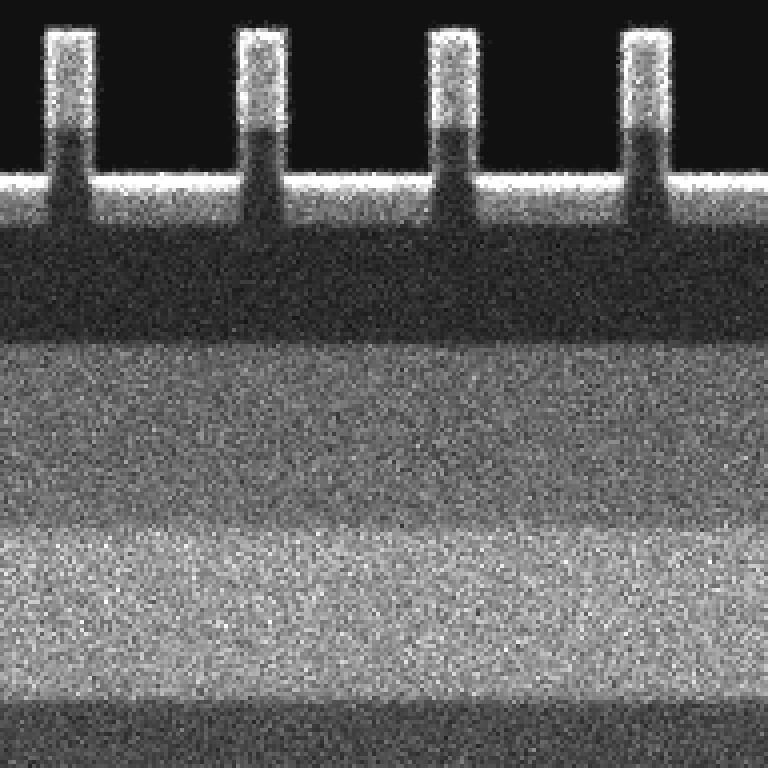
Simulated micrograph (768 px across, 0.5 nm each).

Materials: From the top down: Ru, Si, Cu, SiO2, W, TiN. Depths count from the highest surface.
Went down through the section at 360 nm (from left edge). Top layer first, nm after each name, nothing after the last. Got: empty 72, SiO2 24, Si 60, Cu 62, SiO2 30, W 86, TiN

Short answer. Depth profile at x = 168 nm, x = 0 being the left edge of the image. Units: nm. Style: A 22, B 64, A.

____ empty 72, SiO2 24, Si 60, Cu 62, SiO2 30, W 86, TiN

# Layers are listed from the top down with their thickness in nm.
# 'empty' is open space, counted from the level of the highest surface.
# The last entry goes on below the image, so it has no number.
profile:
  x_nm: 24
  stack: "Ru 48, Si 108, Cu 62, SiO2 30, W 86, TiN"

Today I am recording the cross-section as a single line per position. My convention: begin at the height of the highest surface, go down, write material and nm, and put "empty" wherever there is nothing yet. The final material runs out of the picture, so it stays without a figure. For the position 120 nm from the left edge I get Ru 48, Si 108, Cu 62, SiO2 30, W 86, TiN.